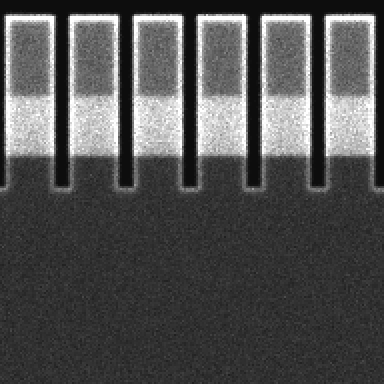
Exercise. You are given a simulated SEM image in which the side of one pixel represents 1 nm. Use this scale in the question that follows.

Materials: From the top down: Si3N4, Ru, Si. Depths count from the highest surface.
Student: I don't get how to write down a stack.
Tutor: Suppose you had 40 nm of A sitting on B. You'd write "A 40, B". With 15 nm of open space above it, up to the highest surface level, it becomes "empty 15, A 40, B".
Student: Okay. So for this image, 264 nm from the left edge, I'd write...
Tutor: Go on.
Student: Si3N4 80, Ru 60, Si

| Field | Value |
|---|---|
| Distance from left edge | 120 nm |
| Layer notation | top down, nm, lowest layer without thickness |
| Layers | empty 172, Si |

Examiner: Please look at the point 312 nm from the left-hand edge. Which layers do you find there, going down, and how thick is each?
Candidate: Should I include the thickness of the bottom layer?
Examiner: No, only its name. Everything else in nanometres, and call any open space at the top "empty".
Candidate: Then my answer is empty 172, Si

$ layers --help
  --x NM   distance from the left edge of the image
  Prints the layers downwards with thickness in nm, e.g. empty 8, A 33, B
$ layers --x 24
Si3N4 80, Ru 60, Si